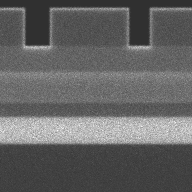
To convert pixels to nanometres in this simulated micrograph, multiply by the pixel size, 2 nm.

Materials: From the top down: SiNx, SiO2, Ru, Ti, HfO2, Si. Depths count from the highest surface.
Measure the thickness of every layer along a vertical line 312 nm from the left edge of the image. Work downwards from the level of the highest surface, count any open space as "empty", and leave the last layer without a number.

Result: SiNx 76, SiO2 52, Ru 62, Ti 28, HfO2 54, Si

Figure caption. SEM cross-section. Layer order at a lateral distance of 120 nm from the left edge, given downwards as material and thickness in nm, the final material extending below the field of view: SiNx 76, SiO2 52, Ru 62, Ti 28, HfO2 54, Si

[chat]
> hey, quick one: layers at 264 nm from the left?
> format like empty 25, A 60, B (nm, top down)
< empty 76, SiO2 52, Ru 62, Ti 28, HfO2 54, Si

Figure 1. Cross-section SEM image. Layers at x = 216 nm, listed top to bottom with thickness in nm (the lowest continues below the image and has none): SiNx 76, SiO2 52, Ru 62, Ti 28, HfO2 54, Si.